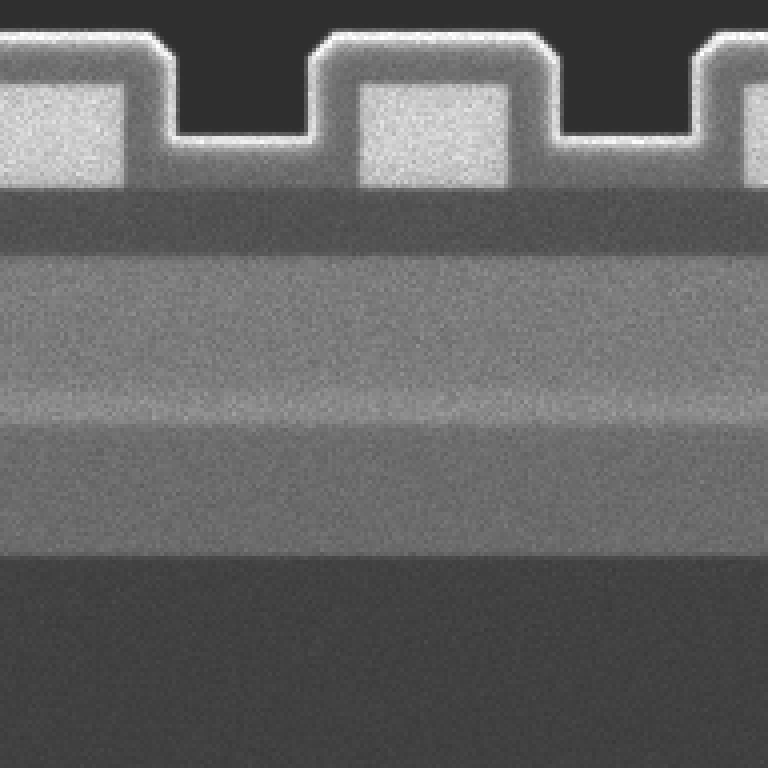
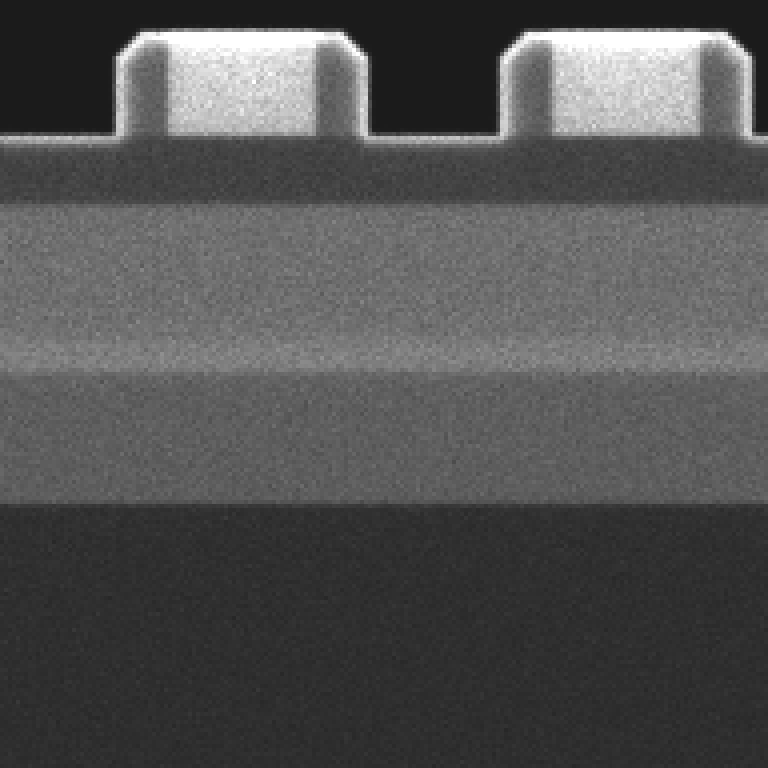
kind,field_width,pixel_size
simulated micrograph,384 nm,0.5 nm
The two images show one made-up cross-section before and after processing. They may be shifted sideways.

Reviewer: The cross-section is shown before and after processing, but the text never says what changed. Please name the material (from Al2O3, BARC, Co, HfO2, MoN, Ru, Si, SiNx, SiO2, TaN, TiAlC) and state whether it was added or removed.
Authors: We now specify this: SiO2, removed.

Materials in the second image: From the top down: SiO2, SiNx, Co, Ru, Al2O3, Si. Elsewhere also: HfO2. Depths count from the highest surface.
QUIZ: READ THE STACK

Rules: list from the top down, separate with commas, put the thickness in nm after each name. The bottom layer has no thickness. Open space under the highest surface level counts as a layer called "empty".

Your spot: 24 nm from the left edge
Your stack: empty 52, SiNx 34, Co 68, Ru 16, Al2O3 66, Si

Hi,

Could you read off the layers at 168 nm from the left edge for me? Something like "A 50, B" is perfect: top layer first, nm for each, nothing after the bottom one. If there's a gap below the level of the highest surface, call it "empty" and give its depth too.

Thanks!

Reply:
SiO2 52, SiNx 34, Co 68, Ru 16, Al2O3 66, Si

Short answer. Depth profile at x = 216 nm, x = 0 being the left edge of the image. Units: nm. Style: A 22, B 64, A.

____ empty 52, SiNx 34, Co 68, Ru 16, Al2O3 66, Si